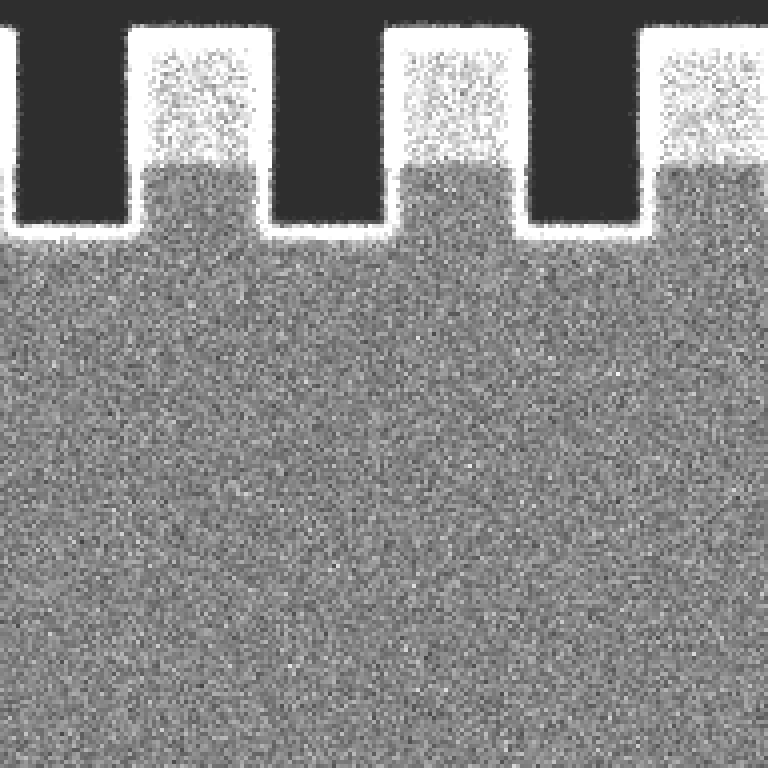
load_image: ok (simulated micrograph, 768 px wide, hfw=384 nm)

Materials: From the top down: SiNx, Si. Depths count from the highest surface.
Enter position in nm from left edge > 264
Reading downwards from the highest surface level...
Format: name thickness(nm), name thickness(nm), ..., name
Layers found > empty 98, Si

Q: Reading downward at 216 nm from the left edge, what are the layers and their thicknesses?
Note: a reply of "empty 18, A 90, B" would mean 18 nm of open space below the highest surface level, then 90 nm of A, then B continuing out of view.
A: SiNx 66, Si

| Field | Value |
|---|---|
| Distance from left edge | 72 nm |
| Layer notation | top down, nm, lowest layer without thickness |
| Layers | SiNx 66, Si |